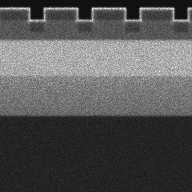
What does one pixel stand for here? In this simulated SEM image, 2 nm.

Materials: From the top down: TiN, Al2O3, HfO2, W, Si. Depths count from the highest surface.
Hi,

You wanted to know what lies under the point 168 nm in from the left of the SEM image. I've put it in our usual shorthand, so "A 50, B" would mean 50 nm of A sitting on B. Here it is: empty 24, TiN 24, Al2O3 16, HfO2 72, W 80, Si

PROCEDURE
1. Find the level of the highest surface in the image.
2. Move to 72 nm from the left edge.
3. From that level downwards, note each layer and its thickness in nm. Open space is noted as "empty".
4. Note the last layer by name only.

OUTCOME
empty 24, TiN 24, Al2O3 16, HfO2 72, W 80, Si